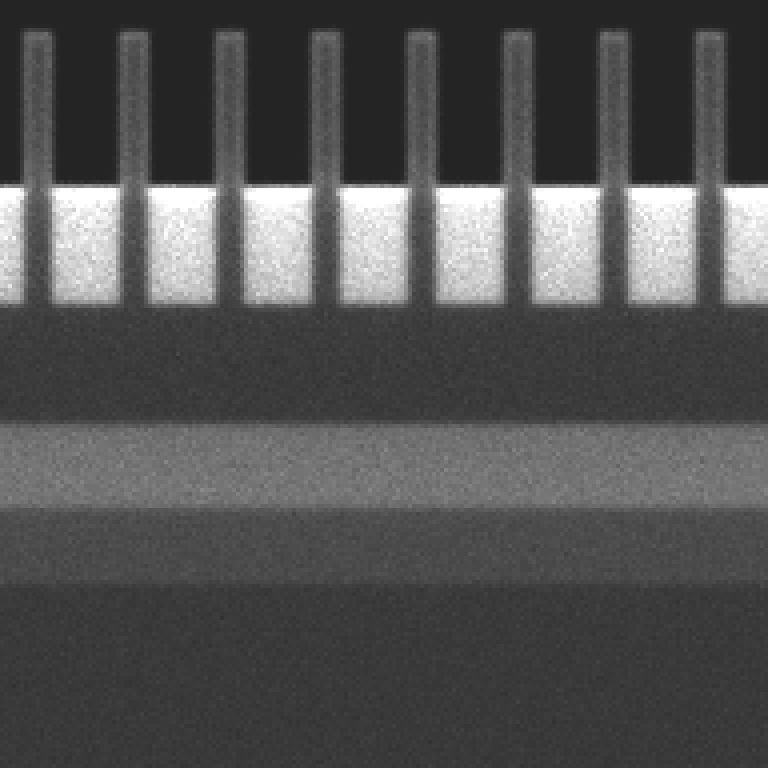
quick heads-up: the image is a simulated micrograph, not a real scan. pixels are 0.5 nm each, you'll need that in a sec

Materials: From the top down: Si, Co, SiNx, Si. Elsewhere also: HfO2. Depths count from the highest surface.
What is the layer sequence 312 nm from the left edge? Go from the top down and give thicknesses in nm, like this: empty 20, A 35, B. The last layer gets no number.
Si 196, Co 42, SiNx 38, Si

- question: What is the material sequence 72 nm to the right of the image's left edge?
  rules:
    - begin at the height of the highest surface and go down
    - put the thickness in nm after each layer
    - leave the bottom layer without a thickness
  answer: Si 196, Co 42, SiNx 38, Si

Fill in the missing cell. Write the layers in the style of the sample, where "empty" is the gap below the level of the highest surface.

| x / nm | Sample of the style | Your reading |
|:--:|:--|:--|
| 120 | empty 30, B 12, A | Si 196, Co 42, SiNx 38, Si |